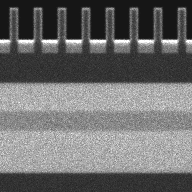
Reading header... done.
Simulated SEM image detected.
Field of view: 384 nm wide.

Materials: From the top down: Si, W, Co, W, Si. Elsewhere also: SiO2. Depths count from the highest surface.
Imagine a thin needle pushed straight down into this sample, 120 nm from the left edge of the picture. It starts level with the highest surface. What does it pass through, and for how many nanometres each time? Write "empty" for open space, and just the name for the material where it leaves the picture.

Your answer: Si 150, W 56, Co 40, W 84, Si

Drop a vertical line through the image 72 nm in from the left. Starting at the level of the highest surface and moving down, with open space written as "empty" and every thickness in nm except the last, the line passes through Si 150, W 56, Co 40, W 84, Si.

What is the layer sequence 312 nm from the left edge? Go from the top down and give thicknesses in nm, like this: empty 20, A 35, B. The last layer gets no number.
Si 150, W 56, Co 40, W 84, Si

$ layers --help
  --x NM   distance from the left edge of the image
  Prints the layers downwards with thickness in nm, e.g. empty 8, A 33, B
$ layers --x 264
Si 150, W 56, Co 40, W 84, Si